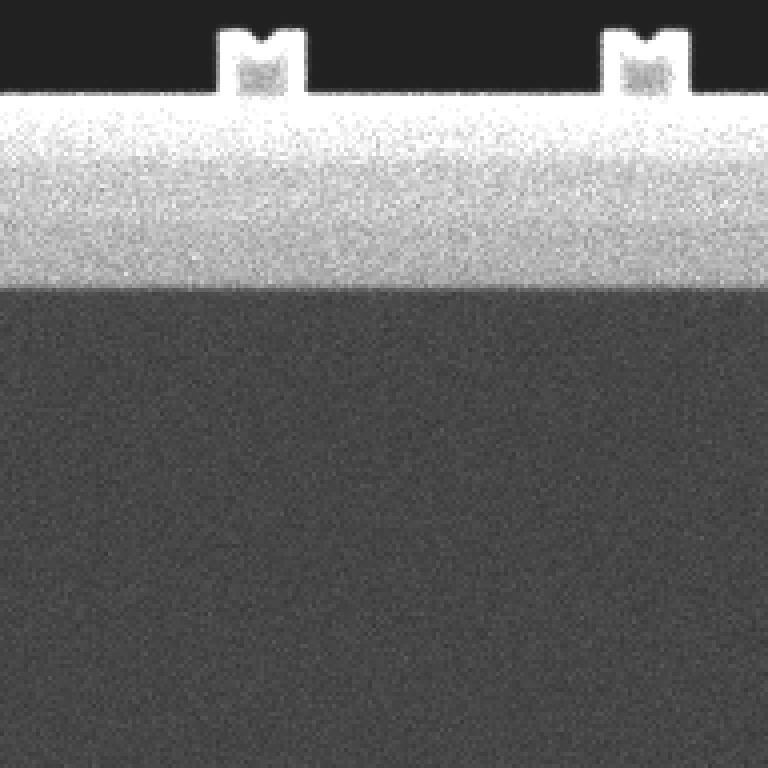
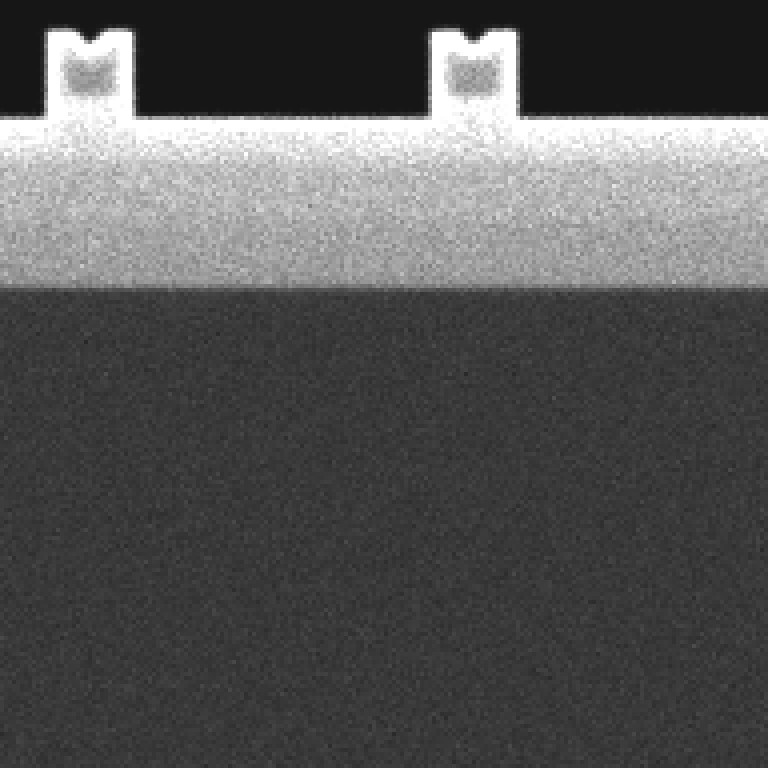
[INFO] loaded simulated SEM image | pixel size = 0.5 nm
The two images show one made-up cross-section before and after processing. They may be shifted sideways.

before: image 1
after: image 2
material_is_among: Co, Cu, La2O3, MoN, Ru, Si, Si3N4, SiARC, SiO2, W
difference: W, removed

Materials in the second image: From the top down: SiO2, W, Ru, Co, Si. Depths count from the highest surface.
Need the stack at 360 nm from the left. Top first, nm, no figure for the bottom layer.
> empty 44, W 20, Ru 30, Co 34, Si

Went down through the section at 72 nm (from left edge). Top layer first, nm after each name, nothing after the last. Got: empty 44, W 20, Ru 30, Co 34, Si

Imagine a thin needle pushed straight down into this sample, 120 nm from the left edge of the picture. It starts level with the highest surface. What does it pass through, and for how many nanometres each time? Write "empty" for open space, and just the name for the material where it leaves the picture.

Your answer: empty 44, W 20, Ru 30, Co 34, Si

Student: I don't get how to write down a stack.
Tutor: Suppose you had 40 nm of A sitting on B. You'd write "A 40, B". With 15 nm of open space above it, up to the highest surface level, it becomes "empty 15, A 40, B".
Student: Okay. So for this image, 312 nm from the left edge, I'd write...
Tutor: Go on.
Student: empty 44, W 20, Ru 30, Co 34, Si